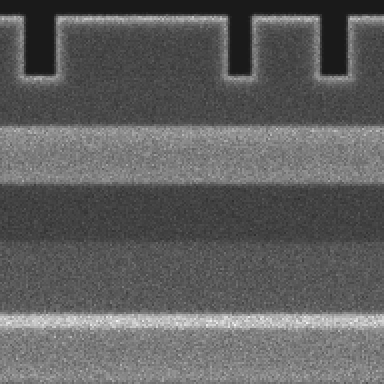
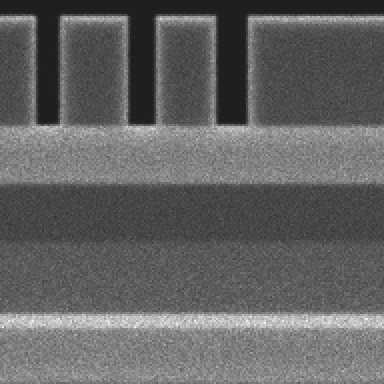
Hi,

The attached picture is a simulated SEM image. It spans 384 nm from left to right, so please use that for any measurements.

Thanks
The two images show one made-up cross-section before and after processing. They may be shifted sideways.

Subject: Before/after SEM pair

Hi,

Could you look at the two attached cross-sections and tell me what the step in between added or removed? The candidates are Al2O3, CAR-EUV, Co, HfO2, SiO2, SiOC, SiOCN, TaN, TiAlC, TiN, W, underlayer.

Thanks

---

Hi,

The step removed underlayer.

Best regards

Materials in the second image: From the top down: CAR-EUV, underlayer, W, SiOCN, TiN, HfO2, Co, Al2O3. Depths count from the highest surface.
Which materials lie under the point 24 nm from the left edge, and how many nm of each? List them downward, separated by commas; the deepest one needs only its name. CAR-EUV 60, underlayer 50, W 58, SiOCN 58, TiN 72, HfO2 14, Co 54, Al2O3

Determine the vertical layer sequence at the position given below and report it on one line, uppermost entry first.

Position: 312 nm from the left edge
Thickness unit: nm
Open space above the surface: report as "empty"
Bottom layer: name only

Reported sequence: CAR-EUV 60, underlayer 50, W 58, SiOCN 58, TiN 72, HfO2 14, Co 54, Al2O3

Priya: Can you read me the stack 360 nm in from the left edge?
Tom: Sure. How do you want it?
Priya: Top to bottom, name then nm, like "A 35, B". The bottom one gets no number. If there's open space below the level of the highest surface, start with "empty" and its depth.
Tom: CAR-EUV 60, underlayer 50, W 58, SiOCN 58, TiN 72, HfO2 14, Co 54, Al2O3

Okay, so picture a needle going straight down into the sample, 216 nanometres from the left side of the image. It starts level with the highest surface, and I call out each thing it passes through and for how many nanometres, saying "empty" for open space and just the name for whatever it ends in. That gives empty 110, W 58, SiOCN 58, TiN 72, HfO2 14, Co 54, Al2O3